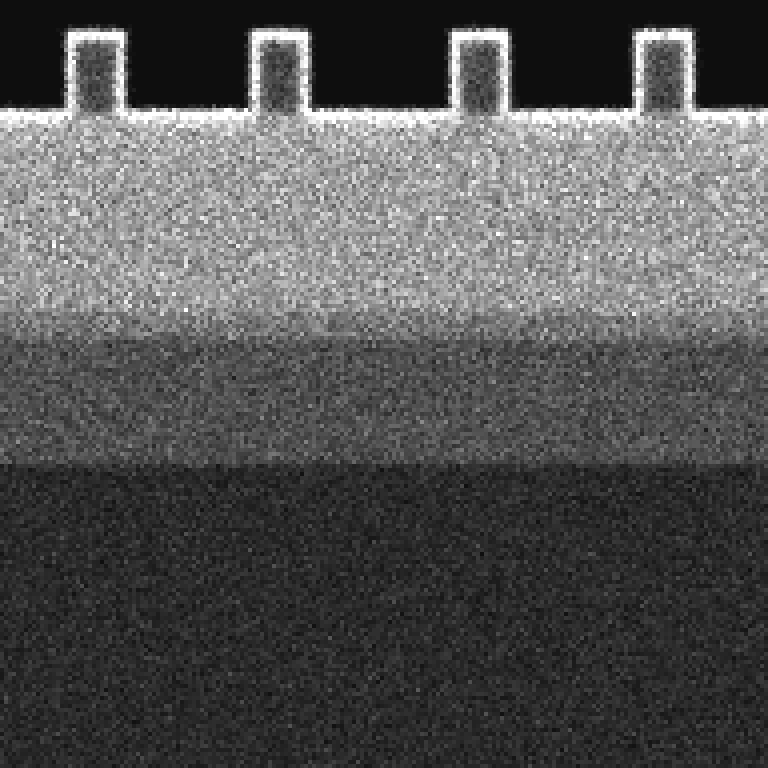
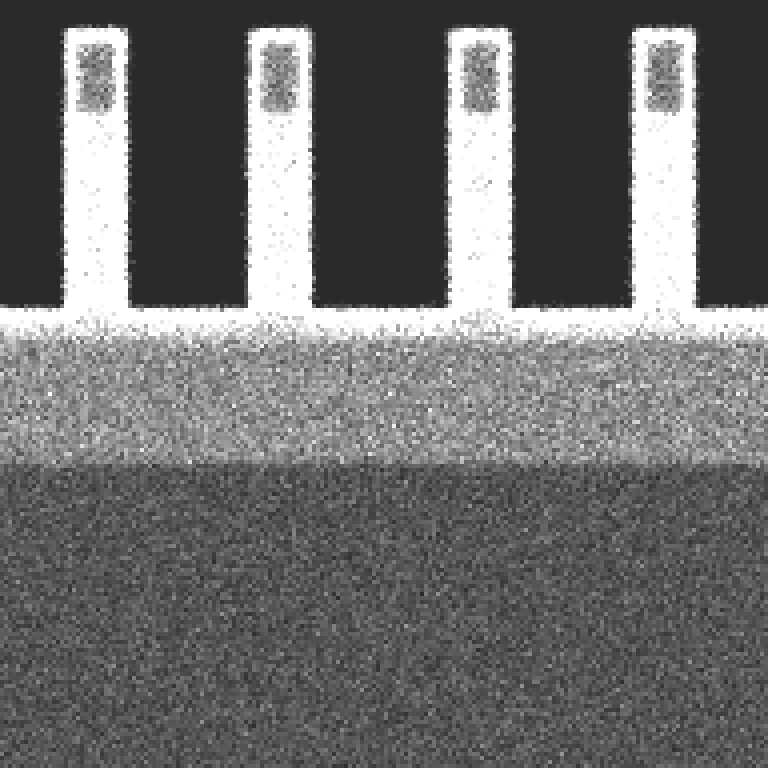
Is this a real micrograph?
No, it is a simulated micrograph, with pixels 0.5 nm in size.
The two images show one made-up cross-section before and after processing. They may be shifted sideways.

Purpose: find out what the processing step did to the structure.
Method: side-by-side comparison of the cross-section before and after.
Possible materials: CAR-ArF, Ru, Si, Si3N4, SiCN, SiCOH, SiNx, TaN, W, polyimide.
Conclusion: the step removed W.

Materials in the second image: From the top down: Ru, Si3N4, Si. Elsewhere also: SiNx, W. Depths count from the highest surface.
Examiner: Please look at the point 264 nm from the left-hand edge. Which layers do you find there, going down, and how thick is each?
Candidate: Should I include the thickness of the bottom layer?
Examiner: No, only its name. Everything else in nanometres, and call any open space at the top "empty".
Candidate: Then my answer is empty 140, Ru 14, Si3N4 62, Si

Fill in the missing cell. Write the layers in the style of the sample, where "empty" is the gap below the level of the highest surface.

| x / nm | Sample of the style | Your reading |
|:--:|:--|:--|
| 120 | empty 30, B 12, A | empty 140, Ru 14, Si3N4 62, Si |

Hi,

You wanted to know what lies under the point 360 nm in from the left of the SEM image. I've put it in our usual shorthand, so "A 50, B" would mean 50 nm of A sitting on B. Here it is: empty 140, Ru 14, Si3N4 62, Si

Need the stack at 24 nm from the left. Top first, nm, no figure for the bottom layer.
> empty 140, Ru 14, Si3N4 62, Si